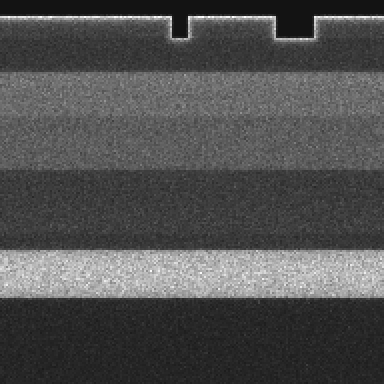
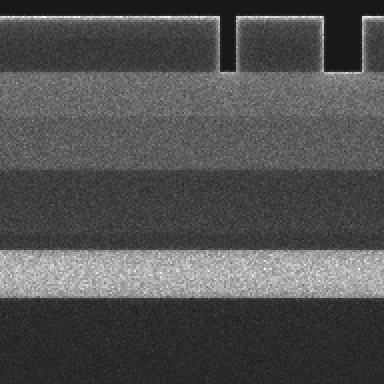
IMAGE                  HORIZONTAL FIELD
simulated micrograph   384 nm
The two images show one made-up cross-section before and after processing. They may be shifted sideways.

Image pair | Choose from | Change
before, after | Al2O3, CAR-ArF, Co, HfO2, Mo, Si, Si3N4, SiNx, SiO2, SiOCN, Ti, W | SiNx (removed)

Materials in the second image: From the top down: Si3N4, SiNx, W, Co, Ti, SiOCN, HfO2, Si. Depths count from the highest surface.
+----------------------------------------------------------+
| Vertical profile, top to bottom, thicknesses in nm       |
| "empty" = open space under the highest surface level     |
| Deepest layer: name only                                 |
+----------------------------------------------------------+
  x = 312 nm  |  Si3N4 22, SiNx 34, W 44, Co 54, Ti 64, SiOCN 16, HfO2 48, Si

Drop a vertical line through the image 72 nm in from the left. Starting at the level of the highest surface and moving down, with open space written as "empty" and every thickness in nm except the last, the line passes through Si3N4 22, SiNx 34, W 44, Co 54, Ti 64, SiOCN 16, HfO2 48, Si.